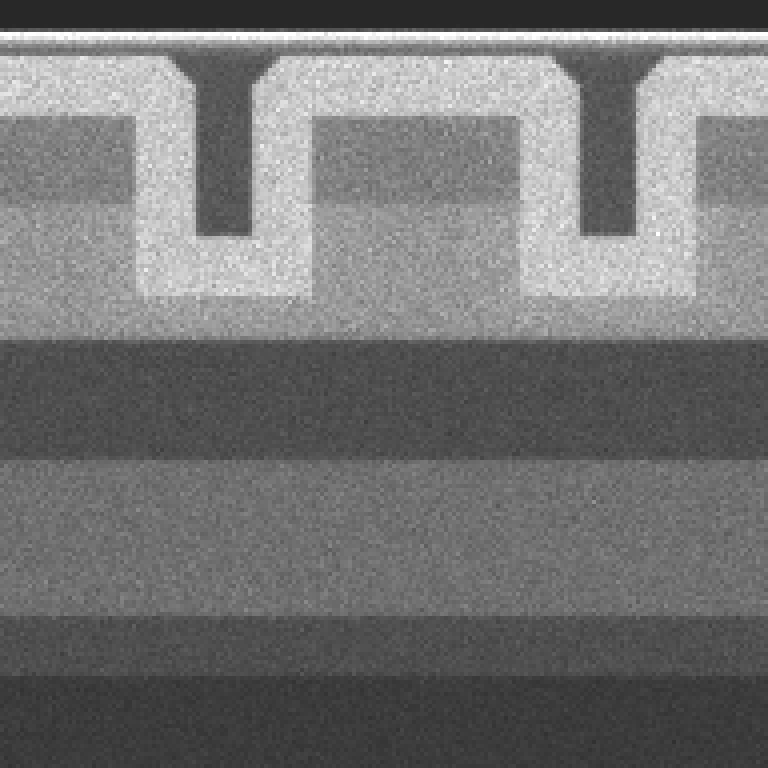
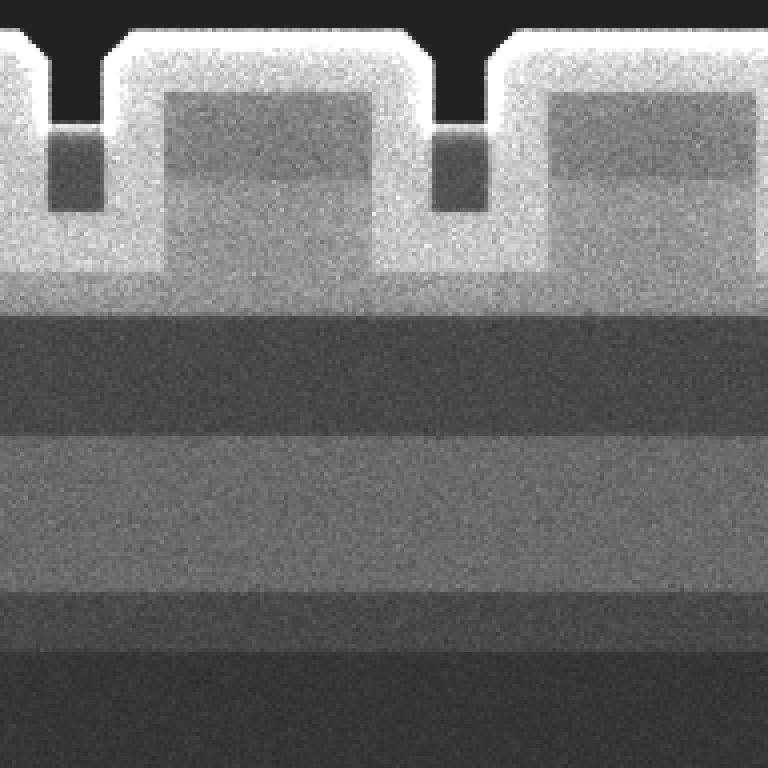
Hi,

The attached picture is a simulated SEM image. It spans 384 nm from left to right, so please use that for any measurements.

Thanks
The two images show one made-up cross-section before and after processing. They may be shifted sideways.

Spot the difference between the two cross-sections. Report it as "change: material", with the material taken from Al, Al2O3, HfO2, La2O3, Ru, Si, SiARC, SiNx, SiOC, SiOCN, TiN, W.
removed: SiARC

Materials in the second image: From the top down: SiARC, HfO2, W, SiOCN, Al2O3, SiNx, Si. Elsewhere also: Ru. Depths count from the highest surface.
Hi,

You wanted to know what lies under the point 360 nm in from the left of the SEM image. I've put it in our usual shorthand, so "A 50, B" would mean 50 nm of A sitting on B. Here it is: HfO2 30, Ru 44, W 68, SiOCN 60, Al2O3 78, SiNx 30, Si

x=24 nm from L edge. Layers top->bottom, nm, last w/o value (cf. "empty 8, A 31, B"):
empty 46, SiARC 44, HfO2 30, W 22, SiOCN 60, Al2O3 78, SiNx 30, Si